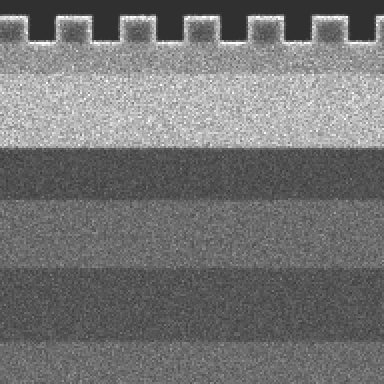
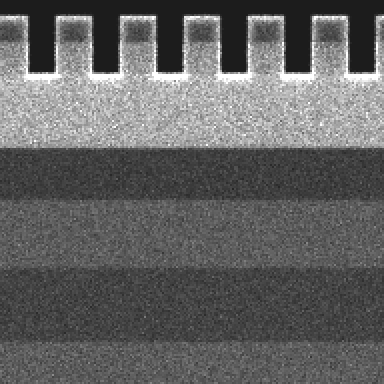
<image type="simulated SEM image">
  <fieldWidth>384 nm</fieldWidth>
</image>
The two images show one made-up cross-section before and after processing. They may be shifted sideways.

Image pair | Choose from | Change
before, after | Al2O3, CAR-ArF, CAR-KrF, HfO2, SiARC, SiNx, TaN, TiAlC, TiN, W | W (removed)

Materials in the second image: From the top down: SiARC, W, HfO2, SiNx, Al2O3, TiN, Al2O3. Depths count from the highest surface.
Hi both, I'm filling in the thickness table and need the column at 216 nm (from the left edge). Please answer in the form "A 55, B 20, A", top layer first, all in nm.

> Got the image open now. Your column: SiARC 26, W 32, HfO2 74, SiNx 52, Al2O3 68, TiN 74, Al2O3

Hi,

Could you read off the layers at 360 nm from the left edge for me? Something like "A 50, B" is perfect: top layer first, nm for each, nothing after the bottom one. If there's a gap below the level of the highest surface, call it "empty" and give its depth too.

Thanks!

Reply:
empty 58, HfO2 74, SiNx 52, Al2O3 68, TiN 74, Al2O3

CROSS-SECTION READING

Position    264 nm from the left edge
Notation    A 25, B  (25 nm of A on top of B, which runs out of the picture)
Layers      SiARC 26, W 32, HfO2 74, SiNx 52, Al2O3 68, TiN 74, Al2O3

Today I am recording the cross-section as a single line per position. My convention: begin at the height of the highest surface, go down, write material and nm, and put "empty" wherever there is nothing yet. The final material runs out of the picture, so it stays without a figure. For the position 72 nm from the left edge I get SiARC 26, W 32, HfO2 74, SiNx 52, Al2O3 68, TiN 74, Al2O3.